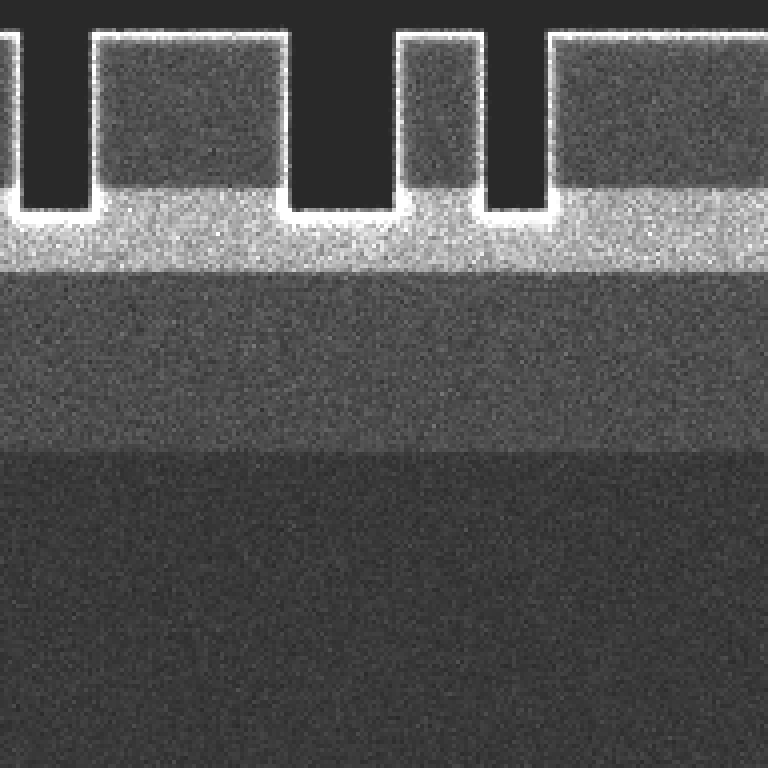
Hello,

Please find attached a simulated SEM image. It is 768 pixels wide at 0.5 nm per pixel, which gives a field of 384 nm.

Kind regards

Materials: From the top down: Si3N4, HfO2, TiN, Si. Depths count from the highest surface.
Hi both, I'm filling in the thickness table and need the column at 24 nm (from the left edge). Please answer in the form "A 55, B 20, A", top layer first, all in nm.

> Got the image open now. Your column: empty 90, HfO2 30, TiN 90, Si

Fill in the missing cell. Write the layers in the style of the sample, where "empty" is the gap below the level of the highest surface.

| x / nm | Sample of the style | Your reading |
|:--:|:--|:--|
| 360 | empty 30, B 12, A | Si3N4 78, HfO2 42, TiN 90, Si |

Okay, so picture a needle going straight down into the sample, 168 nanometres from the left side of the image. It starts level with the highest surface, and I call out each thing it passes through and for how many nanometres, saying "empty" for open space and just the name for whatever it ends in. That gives empty 90, HfO2 30, TiN 90, Si